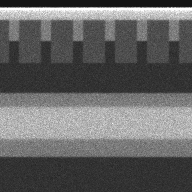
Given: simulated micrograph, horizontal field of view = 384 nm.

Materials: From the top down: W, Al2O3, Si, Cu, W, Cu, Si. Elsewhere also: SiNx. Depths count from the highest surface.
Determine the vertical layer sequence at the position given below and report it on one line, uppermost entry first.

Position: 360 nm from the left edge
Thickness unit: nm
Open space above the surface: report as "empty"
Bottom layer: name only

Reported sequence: W 24, SiNx 86, Si 60, Cu 28, W 64, Cu 36, Si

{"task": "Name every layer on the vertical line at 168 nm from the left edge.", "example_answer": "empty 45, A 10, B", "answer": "W 24, SiNx 86, Si 60, Cu 28, W 64, Cu 36, Si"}